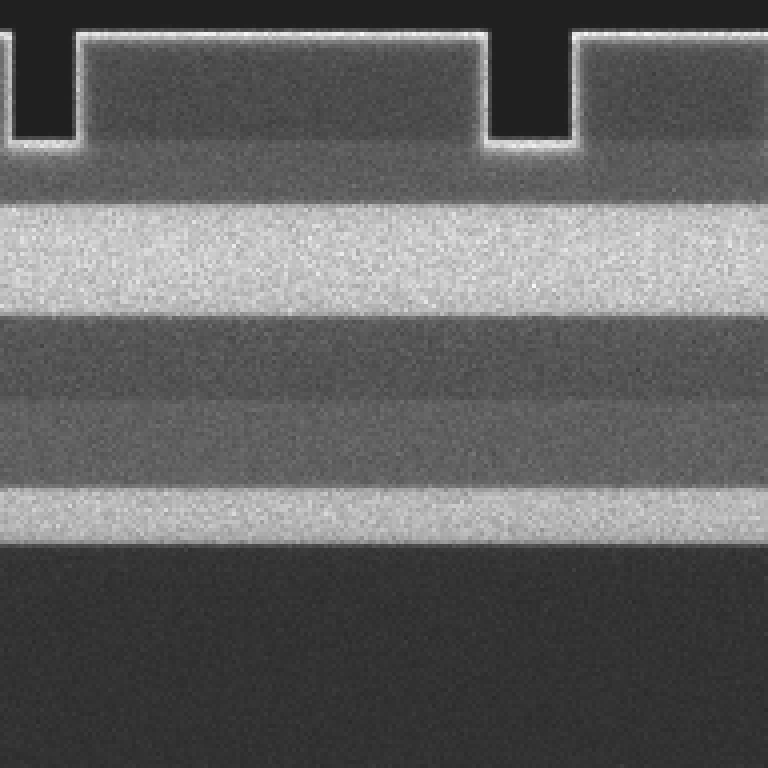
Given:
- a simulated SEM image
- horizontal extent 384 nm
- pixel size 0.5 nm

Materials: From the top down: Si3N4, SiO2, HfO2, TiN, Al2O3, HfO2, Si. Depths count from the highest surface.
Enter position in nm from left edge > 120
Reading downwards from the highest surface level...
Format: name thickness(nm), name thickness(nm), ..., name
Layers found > Si3N4 54, SiO2 32, HfO2 56, TiN 42, Al2O3 44, HfO2 28, Si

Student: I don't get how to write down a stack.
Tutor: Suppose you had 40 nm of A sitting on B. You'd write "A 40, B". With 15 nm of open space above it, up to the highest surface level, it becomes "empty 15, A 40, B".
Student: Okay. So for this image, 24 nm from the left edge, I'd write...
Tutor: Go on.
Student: empty 54, SiO2 32, HfO2 56, TiN 42, Al2O3 44, HfO2 28, Si